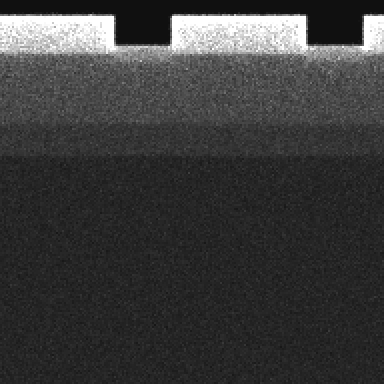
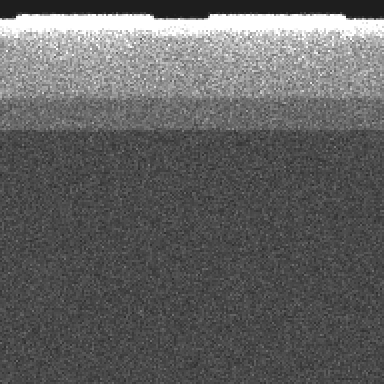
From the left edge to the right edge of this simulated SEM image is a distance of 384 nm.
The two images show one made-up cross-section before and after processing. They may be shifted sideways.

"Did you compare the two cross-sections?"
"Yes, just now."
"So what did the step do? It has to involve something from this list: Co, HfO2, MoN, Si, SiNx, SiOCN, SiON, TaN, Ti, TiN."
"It removed HfO2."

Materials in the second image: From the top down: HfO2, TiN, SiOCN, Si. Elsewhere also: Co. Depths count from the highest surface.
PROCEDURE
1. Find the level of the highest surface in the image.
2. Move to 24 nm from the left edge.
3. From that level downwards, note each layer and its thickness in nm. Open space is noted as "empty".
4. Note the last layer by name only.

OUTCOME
HfO2 12, TiN 70, SiOCN 32, Si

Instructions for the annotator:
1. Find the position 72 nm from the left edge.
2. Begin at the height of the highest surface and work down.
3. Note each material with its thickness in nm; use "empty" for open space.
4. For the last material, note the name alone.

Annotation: HfO2 12, TiN 70, SiOCN 32, Si